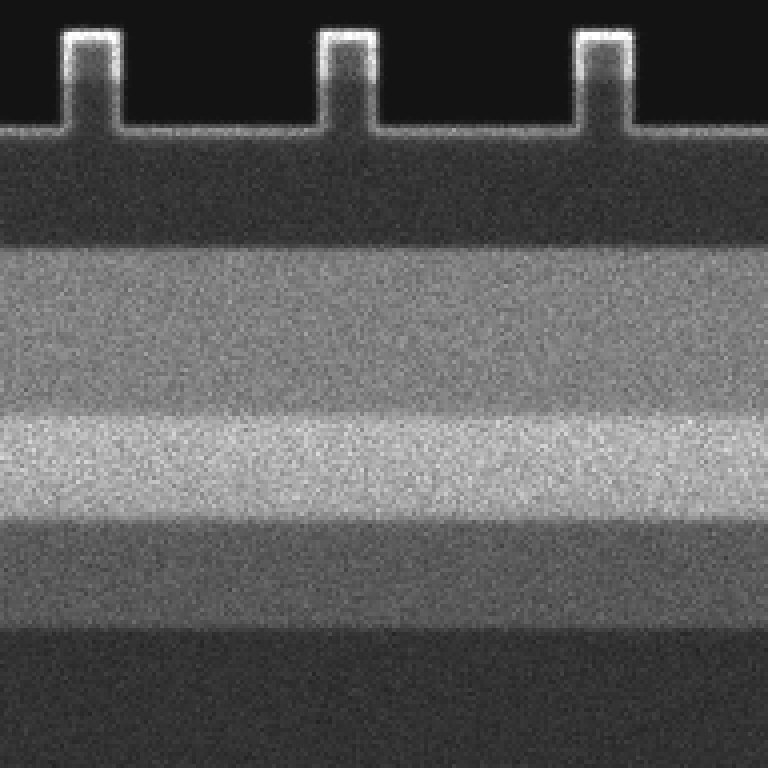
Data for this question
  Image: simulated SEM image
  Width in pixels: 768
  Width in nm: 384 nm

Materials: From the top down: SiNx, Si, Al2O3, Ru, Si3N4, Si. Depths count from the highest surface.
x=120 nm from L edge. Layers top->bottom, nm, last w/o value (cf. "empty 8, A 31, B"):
empty 48, Si 60, Al2O3 84, Ru 52, Si3N4 54, Si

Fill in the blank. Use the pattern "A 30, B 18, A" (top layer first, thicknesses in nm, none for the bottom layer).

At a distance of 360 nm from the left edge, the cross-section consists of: empty 48, Si 60, Al2O3 84, Ru 52, Si3N4 54, Si